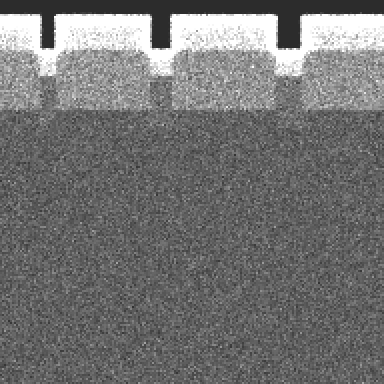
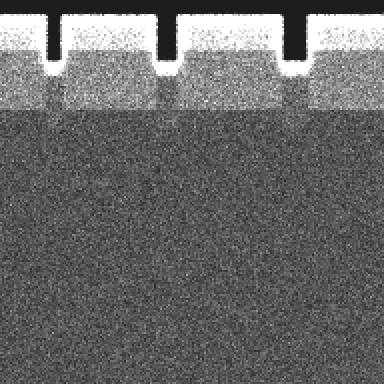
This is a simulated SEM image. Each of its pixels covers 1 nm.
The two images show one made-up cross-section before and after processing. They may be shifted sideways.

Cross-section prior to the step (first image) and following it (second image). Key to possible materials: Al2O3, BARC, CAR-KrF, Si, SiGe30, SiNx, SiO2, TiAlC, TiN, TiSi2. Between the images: SiO2 was removed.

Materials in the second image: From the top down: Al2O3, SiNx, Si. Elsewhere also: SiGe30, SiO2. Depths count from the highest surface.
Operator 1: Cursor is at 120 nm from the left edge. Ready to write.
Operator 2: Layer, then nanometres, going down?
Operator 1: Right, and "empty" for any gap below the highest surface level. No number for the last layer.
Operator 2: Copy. Al2O3 34, SiNx 60, Si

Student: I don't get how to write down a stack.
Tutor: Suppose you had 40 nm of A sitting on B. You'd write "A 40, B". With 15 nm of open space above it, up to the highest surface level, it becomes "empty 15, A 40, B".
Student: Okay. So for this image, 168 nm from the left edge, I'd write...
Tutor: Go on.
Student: empty 46, SiO2 14, SiGe30 52, Si